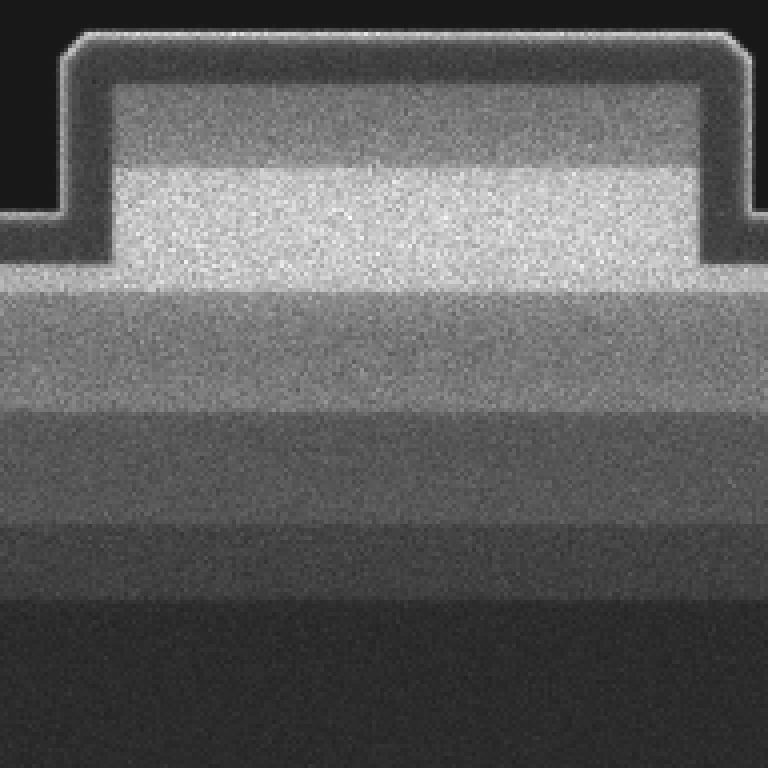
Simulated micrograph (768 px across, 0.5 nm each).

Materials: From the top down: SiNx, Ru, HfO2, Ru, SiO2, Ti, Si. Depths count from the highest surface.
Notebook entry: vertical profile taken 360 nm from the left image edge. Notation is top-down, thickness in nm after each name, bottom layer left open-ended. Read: SiNx 116, HfO2 14, Ru 60, SiO2 56, Ti 38, Si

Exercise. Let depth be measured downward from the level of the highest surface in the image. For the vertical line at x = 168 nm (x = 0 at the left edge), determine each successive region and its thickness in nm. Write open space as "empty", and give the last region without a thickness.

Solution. SiNx 26, Ru 42, HfO2 62, Ru 60, SiO2 56, Ti 38, Si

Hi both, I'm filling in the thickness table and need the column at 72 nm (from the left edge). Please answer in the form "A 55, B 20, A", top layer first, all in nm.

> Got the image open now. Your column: SiNx 26, Ru 42, HfO2 62, Ru 60, SiO2 56, Ti 38, Si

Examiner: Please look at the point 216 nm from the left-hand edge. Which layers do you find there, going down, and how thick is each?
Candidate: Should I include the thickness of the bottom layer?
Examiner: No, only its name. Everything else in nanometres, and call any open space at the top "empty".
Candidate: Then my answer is SiNx 26, Ru 42, HfO2 62, Ru 60, SiO2 56, Ti 38, Si